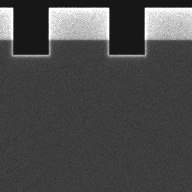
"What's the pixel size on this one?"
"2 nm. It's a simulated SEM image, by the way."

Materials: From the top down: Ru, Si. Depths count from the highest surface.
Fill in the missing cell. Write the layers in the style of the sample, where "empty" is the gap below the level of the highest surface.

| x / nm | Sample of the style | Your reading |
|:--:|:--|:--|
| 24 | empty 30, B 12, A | Ru 64, Si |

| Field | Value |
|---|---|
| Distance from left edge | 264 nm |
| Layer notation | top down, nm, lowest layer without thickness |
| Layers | empty 94, Si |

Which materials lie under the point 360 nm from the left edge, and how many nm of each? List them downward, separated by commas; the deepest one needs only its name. Ru 64, Si